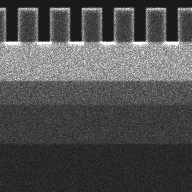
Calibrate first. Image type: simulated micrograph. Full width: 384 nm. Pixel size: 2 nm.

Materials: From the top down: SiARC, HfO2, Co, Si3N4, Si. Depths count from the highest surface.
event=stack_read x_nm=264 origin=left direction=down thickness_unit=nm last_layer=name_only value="SiARC 68, HfO2 78, Co 48, Si3N4 78, Si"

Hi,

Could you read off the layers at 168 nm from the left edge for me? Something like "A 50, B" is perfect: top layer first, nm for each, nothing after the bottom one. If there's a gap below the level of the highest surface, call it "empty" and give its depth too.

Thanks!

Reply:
SiARC 68, HfO2 78, Co 48, Si3N4 78, Si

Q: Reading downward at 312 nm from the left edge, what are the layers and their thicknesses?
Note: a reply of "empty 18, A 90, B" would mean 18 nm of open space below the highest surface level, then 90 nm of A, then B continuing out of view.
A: SiARC 68, HfO2 78, Co 48, Si3N4 78, Si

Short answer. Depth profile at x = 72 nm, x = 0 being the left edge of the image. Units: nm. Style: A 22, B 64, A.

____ SiARC 68, HfO2 78, Co 48, Si3N4 78, Si